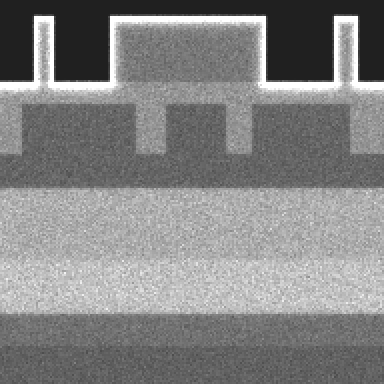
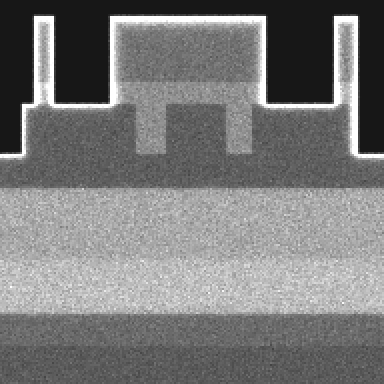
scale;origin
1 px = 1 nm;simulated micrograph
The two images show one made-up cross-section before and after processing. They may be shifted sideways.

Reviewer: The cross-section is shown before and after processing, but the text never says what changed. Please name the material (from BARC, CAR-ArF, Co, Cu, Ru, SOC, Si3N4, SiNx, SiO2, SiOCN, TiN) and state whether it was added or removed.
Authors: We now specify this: SiO2, removed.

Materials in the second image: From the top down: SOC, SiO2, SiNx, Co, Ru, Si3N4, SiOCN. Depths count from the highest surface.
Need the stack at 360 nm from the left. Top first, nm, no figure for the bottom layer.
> empty 138, SiNx 34, Co 72, Ru 54, Si3N4 32, SiOCN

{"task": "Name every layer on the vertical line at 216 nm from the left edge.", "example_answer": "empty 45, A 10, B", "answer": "SOC 66, SiO2 22, SiNx 84, Co 72, Ru 54, Si3N4 32, SiOCN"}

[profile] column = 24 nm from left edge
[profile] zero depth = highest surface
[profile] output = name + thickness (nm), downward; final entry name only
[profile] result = empty 88, SiNx 84, Co 72, Ru 54, Si3N4 32, SiOCN